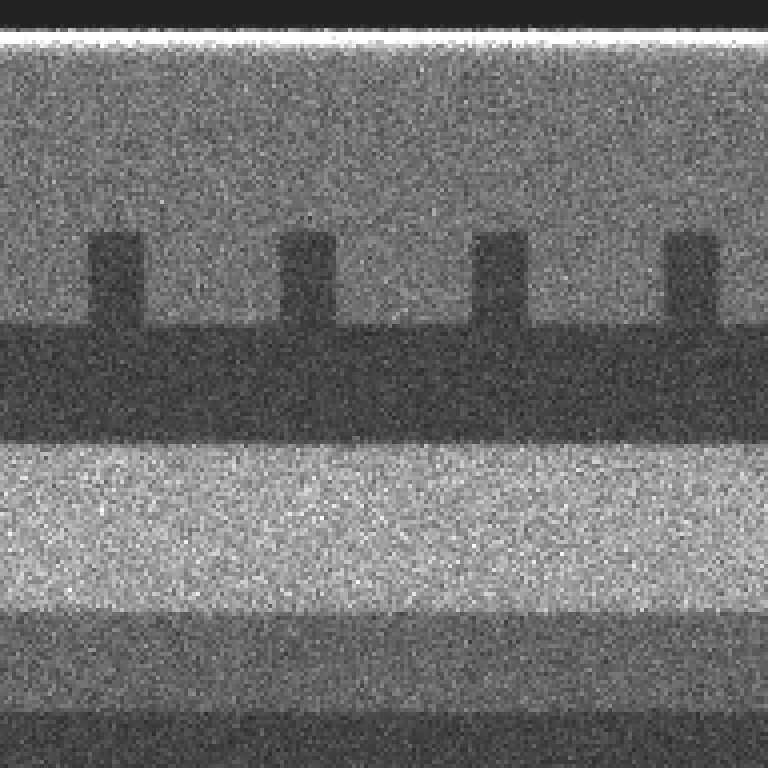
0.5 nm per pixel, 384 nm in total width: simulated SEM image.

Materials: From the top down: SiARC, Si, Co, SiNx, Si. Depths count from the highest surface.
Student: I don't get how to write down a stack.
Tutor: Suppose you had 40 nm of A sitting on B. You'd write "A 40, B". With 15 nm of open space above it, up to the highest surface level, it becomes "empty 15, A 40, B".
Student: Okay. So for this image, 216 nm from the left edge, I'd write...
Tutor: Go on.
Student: SiARC 146, Si 60, Co 84, SiNx 50, Si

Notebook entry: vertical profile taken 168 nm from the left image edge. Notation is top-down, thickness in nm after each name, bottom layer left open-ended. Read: SiARC 146, Si 60, Co 84, SiNx 50, Si